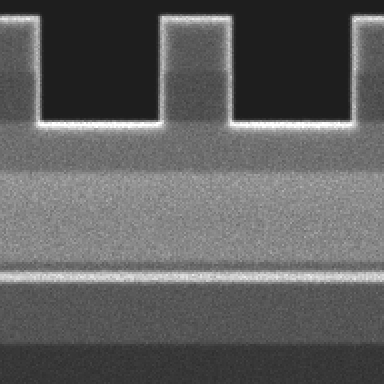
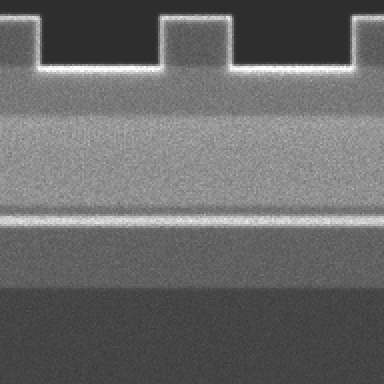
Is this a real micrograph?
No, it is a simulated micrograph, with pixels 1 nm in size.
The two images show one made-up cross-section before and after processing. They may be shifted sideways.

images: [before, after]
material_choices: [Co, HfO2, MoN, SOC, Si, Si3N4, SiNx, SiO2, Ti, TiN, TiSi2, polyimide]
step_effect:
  removed: SOC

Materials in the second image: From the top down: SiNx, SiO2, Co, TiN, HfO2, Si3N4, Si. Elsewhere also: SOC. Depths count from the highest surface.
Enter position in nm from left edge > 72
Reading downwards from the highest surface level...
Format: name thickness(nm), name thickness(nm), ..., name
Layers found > empty 50, SiO2 50, Co 90, TiN 10, HfO2 10, Si3N4 62, Si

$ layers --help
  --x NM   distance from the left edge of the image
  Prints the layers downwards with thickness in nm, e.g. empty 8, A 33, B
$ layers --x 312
empty 50, SiO2 50, Co 90, TiN 10, HfO2 10, Si3N4 62, Si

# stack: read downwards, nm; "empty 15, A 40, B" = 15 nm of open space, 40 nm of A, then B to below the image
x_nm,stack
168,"SiNx 50, SiO2 50, Co 90, TiN 10, HfO2 10, Si3N4 62, Si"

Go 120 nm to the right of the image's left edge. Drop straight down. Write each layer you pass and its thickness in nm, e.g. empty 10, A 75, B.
empty 50, SiO2 50, Co 90, TiN 10, HfO2 10, Si3N4 62, Si